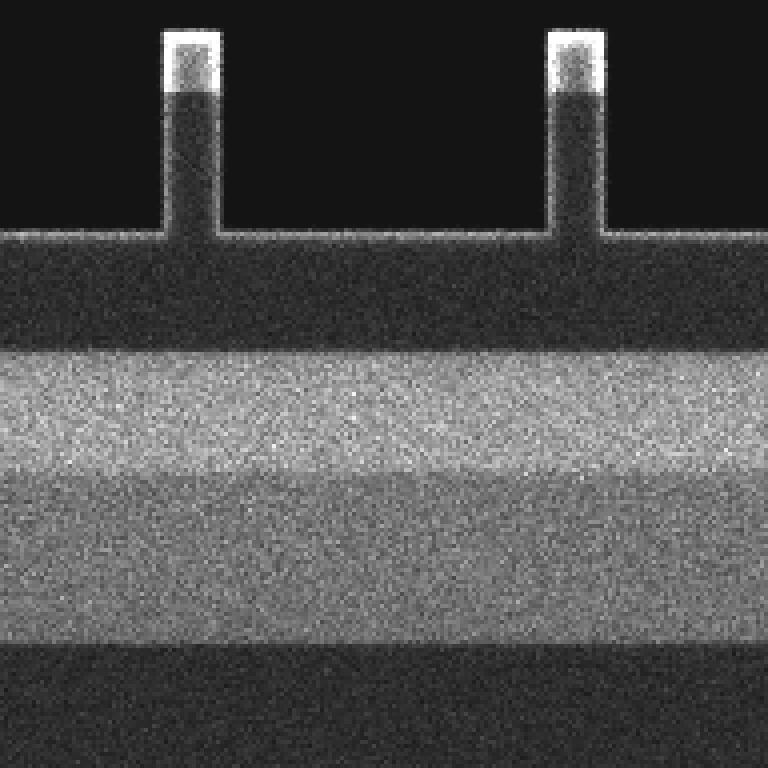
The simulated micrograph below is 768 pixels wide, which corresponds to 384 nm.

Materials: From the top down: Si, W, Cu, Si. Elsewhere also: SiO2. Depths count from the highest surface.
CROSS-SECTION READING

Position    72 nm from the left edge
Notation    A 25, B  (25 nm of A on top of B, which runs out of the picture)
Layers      empty 100, Si 60, W 60, Cu 86, Si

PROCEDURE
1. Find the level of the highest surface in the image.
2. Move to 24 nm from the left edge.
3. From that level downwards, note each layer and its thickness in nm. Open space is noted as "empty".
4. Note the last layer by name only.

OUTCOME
empty 100, Si 60, W 60, Cu 86, Si